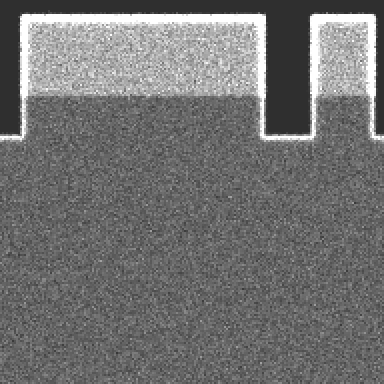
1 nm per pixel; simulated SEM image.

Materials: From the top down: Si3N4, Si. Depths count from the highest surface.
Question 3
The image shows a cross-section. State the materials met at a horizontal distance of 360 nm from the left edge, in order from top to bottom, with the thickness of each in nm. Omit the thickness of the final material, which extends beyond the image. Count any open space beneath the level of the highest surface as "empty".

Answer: Si3N4 80, Si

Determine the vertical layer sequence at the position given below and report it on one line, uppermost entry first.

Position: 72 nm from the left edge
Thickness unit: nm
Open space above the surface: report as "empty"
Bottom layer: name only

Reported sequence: Si3N4 80, Si